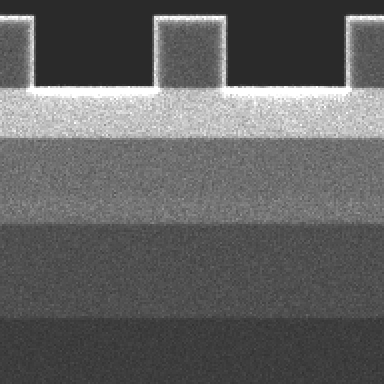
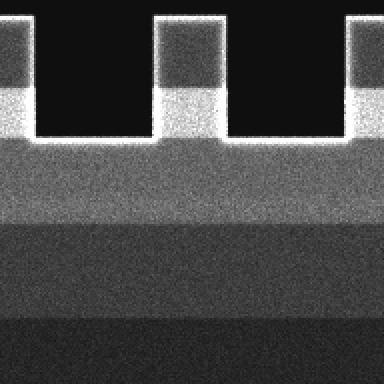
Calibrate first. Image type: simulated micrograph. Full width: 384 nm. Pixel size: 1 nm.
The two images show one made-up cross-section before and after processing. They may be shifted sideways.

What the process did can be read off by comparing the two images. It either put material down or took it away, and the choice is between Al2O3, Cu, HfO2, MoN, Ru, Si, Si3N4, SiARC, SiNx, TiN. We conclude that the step removed HfO2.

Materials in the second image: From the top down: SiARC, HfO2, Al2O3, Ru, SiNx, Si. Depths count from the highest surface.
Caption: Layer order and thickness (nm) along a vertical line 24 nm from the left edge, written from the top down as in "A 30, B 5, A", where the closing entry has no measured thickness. SiARC 72, HfO2 50, Al2O3 58, Ru 28, SiNx 94, Si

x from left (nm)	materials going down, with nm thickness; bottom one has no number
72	empty 122, Al2O3 58, Ru 28, SiNx 94, Si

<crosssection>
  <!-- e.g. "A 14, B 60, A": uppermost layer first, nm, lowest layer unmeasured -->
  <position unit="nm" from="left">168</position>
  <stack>SiARC 72, HfO2 50, Al2O3 58, Ru 28, SiNx 94, Si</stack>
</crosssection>